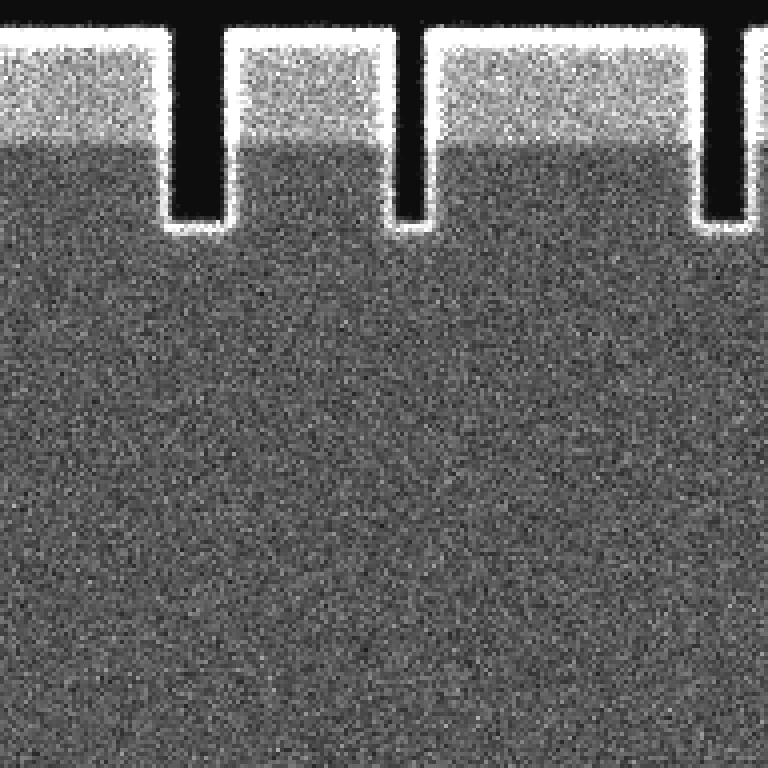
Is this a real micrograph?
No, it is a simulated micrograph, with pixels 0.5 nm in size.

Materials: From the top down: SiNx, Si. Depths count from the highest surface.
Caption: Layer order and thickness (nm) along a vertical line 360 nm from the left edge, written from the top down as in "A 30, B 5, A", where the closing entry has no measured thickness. empty 96, Si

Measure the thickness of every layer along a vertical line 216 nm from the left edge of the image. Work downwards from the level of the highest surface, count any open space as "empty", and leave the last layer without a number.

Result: SiNx 56, Si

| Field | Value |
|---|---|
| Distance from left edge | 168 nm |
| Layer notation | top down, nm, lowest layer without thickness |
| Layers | SiNx 56, Si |